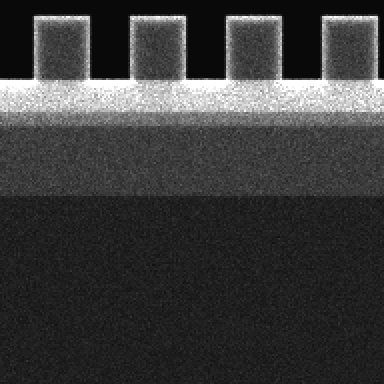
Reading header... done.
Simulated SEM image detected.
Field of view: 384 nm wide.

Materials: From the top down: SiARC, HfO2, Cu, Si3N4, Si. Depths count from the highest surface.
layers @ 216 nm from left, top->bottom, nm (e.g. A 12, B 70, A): empty 64, HfO2 32, Cu 14, Si3N4 70, Si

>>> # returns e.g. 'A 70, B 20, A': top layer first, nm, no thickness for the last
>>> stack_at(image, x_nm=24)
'empty 64, HfO2 32, Cu 14, Si3N4 70, Si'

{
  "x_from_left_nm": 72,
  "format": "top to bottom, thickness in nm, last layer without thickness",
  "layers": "SiARC 64, HfO2 32, Cu 14, Si3N4 70, Si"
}